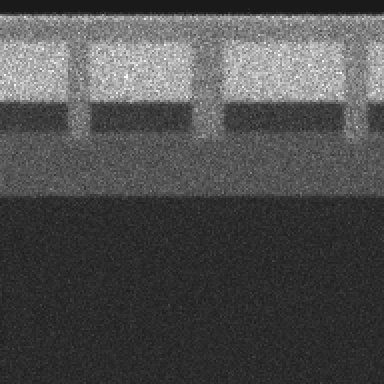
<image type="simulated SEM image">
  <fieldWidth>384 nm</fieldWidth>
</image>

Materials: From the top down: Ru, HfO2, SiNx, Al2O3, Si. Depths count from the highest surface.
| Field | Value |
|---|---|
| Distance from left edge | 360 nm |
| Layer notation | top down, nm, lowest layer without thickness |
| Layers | Ru 124, Al2O3 56, Si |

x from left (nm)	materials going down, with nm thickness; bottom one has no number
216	Ru 124, Al2O3 56, Si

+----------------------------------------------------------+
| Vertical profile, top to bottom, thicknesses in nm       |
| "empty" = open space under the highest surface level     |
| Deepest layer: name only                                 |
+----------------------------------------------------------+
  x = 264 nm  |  Ru 26, HfO2 60, SiNx 30, Al2O3 64, Si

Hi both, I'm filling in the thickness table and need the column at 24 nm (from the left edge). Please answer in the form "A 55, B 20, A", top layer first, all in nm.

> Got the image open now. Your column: Ru 26, HfO2 60, SiNx 30, Al2O3 64, Si